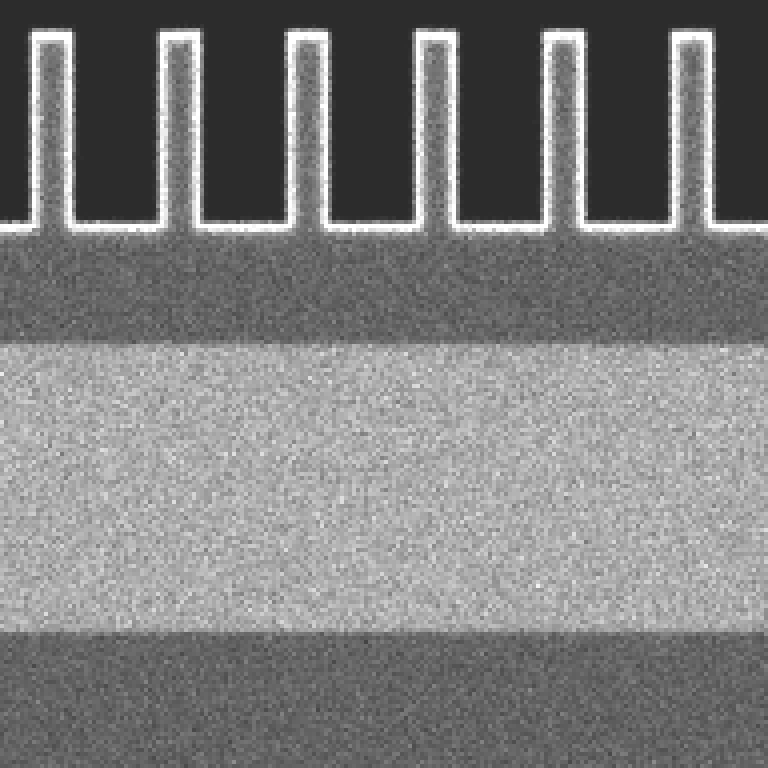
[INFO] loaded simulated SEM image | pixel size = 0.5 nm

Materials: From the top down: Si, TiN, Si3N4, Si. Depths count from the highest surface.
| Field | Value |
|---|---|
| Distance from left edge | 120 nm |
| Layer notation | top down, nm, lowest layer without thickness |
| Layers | empty 96, Si 60, TiN 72, Si3N4 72, Si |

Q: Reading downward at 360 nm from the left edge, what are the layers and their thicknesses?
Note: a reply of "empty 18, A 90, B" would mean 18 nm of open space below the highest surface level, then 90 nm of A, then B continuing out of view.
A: empty 96, Si 60, TiN 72, Si3N4 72, Si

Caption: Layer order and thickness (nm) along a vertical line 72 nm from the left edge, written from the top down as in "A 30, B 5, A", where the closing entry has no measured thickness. empty 96, Si 60, TiN 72, Si3N4 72, Si